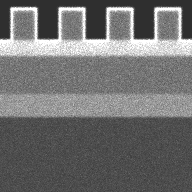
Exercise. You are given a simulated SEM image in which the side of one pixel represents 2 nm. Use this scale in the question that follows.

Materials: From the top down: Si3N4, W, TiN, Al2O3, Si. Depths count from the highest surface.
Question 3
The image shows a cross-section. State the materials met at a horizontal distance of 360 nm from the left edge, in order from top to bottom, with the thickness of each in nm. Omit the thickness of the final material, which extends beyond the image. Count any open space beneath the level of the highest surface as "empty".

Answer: Si3N4 64, W 32, TiN 76, Al2O3 46, Si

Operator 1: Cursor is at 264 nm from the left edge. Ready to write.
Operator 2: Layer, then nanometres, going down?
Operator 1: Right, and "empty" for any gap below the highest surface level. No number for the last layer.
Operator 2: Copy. Si3N4 64, W 32, TiN 76, Al2O3 46, Si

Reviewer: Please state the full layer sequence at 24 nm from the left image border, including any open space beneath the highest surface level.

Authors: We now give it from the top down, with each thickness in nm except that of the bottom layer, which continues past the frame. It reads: Si3N4 64, W 32, TiN 76, Al2O3 46, Si